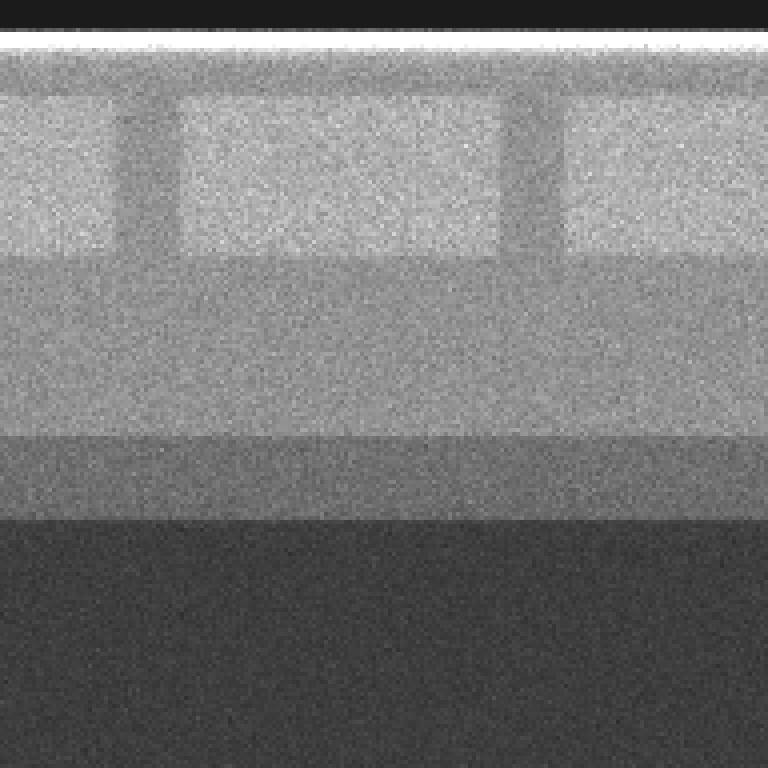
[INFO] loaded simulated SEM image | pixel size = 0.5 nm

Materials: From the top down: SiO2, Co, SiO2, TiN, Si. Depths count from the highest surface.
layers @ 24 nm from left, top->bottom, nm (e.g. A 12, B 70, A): SiO2 32, Co 80, SiO2 90, TiN 42, Si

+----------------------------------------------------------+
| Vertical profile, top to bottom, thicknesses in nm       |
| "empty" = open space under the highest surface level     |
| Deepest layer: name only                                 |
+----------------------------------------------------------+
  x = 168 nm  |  SiO2 32, Co 80, SiO2 90, TiN 42, Si